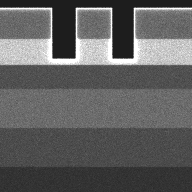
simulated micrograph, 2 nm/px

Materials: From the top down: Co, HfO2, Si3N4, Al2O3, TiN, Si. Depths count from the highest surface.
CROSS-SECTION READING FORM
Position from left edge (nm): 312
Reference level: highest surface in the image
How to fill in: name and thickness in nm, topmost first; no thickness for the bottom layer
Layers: Co 62, HfO2 52, Si3N4 48, Al2O3 78, TiN 78, Si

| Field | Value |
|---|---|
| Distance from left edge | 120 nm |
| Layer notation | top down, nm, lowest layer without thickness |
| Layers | empty 102, HfO2 12, Si3N4 48, Al2O3 78, TiN 78, Si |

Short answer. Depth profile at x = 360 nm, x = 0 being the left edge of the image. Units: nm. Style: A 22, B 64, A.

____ Co 62, HfO2 52, Si3N4 48, Al2O3 78, TiN 78, Si